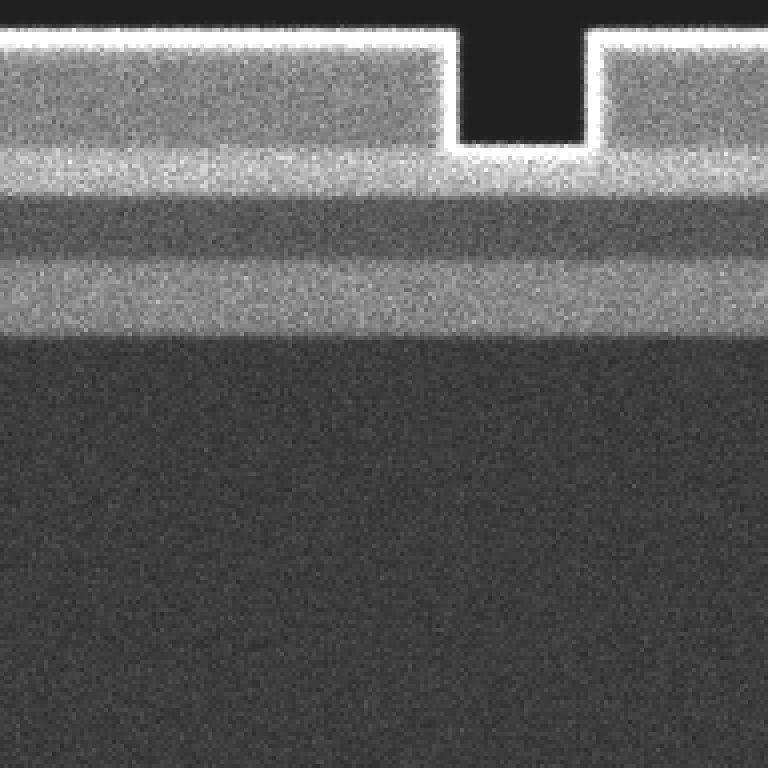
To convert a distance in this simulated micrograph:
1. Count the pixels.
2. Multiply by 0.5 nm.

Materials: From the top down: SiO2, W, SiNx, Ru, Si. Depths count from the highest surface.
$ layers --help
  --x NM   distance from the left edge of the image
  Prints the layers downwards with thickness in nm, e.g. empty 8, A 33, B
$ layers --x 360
SiO2 58, W 24, SiNx 32, Ru 38, Si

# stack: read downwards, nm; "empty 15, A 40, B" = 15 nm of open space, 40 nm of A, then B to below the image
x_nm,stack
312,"SiO2 58, W 24, SiNx 32, Ru 38, Si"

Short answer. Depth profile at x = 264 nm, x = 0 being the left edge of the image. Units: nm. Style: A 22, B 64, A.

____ empty 58, W 24, SiNx 32, Ru 38, Si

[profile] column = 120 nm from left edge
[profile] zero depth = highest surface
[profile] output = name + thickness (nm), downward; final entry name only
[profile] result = SiO2 58, W 24, SiNx 32, Ru 38, Si